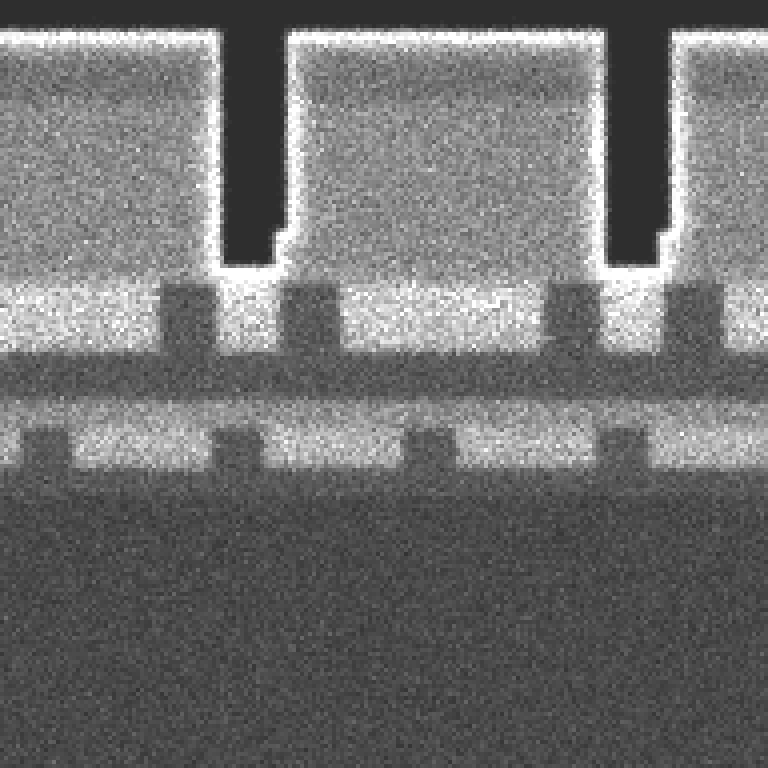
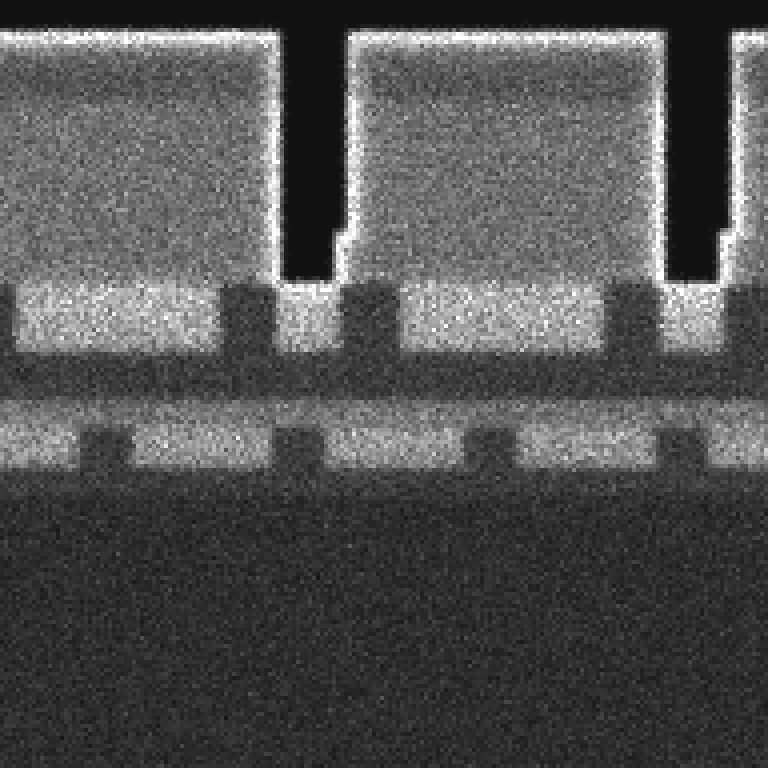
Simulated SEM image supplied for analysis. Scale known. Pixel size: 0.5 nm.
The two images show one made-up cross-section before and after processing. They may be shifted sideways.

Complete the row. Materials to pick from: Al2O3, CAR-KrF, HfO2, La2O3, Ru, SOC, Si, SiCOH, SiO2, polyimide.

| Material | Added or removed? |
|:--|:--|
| Al2O3 | removed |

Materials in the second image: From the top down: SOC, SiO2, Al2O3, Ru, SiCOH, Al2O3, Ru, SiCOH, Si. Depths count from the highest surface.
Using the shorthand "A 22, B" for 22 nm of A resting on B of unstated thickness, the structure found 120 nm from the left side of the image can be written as SOC 34, SiO2 84, Al2O3 8, SiCOH 58, Al2O3 14, Ru 20, SiCOH 14, Si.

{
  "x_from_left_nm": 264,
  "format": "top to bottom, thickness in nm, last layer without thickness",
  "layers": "SOC 34, SiO2 84, Al2O3 8, Ru 34, SiCOH 24, Al2O3 14, Ru 20, SiCOH 14, Si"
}